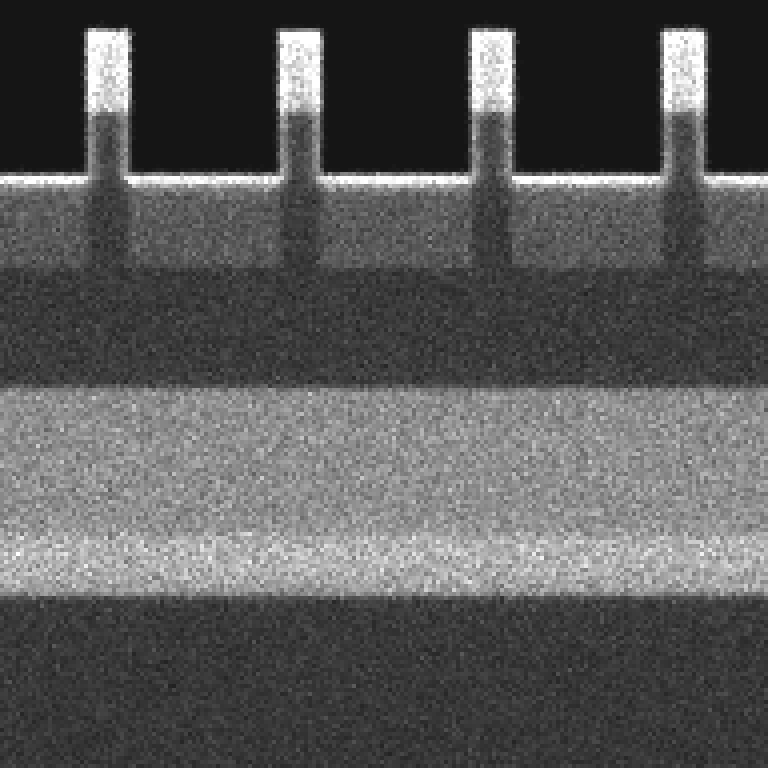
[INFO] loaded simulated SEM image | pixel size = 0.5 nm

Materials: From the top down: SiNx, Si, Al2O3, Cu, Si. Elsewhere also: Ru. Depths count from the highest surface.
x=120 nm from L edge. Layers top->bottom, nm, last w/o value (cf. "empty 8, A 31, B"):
empty 72, SiNx 46, Si 60, Al2O3 74, Cu 30, Si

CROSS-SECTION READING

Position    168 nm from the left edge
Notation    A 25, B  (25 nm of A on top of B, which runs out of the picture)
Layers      empty 72, SiNx 46, Si 60, Al2O3 74, Cu 30, Si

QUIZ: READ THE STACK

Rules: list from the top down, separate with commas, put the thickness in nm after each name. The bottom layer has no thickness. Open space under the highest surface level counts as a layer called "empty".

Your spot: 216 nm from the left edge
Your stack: empty 72, SiNx 46, Si 60, Al2O3 74, Cu 30, Si